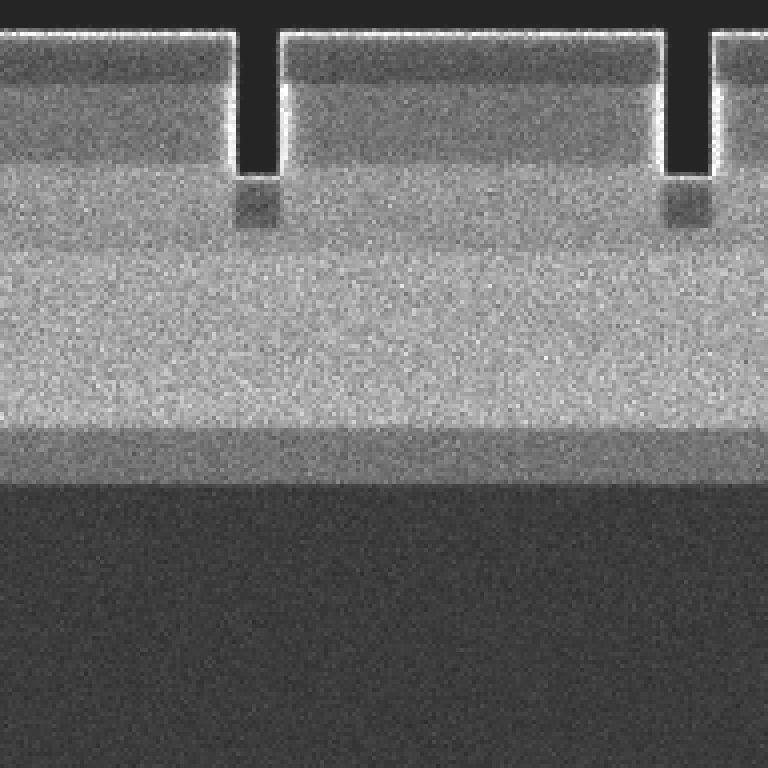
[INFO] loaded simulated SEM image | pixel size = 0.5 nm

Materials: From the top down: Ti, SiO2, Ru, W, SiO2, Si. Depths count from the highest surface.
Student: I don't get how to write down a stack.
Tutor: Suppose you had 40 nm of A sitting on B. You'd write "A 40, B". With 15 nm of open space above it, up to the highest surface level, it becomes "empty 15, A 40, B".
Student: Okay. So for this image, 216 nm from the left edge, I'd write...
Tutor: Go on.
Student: Ti 26, SiO2 40, Ru 44, W 88, SiO2 28, Si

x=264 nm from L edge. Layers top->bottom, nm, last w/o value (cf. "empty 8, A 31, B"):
Ti 26, SiO2 40, Ru 44, W 88, SiO2 28, Si